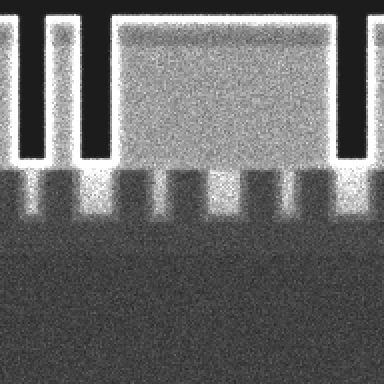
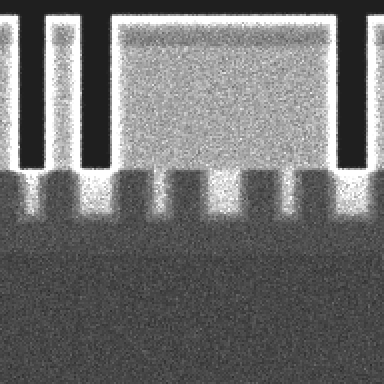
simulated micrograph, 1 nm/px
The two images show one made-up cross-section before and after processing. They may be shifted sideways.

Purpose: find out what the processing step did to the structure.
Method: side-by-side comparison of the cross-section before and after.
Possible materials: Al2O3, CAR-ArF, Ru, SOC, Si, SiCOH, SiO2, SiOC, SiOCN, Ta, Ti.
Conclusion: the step removed Al2O3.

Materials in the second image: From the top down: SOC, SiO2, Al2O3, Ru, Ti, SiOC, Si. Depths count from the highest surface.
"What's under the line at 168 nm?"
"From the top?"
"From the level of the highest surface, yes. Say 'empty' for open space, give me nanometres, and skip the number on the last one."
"SOC 30, SiO2 114, Al2O3 10, Ti 52, SiOC 32, Si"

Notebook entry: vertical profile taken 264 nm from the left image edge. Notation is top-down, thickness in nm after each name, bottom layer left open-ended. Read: SOC 30, SiO2 114, Al2O3 10, SiOC 84, Si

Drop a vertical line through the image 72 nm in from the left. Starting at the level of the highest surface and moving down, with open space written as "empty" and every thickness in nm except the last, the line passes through SOC 30, SiO2 114, Al2O3 10, Ti 52, SiOC 32, Si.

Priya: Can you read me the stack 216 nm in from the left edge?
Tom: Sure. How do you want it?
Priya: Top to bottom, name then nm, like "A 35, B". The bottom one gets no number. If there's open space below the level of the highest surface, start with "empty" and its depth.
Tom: SOC 30, SiO2 114, Al2O3 10, Ru 44, Ti 8, SiOC 32, Si